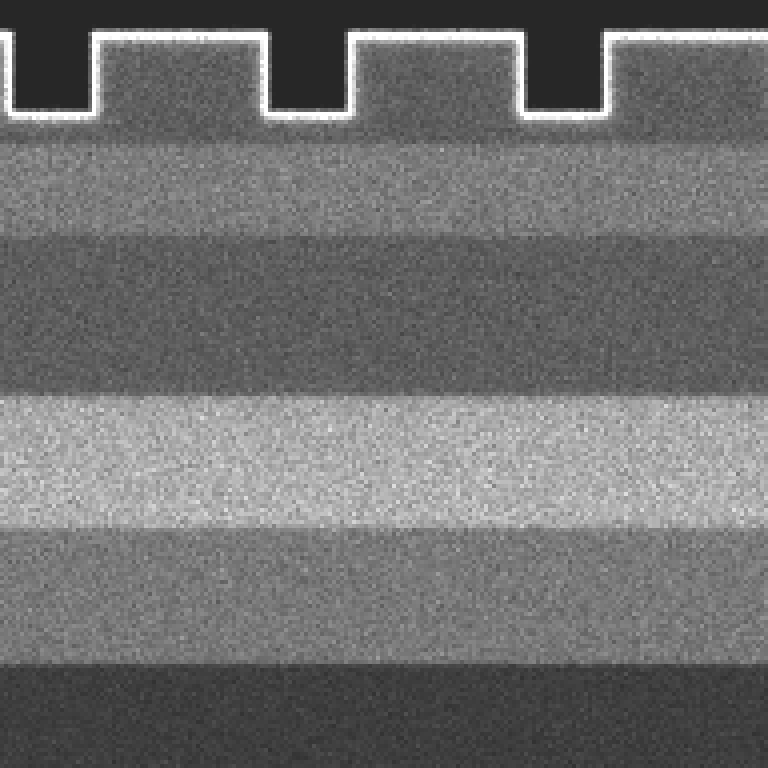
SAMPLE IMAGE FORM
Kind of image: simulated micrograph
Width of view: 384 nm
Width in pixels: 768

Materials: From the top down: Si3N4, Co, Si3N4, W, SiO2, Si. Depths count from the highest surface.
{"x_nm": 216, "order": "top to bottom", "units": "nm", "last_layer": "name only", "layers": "Si3N4 56, Co 46, Si3N4 80, W 66, SiO2 68, Si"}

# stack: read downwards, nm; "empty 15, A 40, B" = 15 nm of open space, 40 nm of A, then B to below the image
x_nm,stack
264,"empty 40, Si3N4 16, Co 46, Si3N4 80, W 66, SiO2 68, Si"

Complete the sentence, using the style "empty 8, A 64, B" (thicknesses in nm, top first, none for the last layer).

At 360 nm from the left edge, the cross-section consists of Si3N4 56, Co 46, Si3N4 80, W 66, SiO2 68, Si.